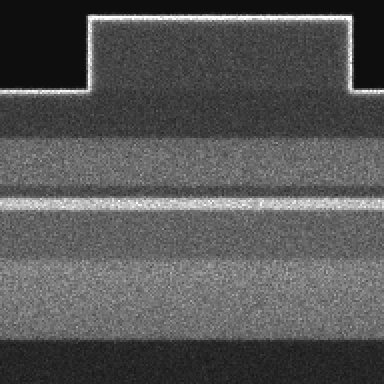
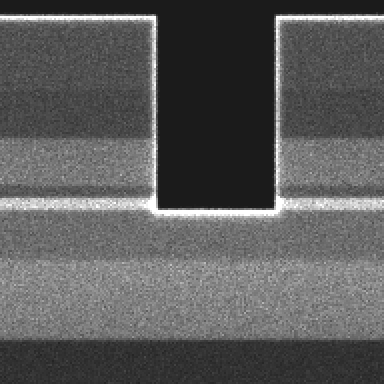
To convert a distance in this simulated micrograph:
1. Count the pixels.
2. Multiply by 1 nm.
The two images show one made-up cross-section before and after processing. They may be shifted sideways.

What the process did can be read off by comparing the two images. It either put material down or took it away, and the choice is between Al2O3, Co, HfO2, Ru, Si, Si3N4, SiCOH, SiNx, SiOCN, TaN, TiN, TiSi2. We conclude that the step removed Co and HfO2 and SiNx and TiN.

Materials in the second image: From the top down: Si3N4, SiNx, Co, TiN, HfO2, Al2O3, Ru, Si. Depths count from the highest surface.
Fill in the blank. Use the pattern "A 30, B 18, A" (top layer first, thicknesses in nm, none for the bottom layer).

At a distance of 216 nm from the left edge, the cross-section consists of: empty 194, Al2O3 50, Ru 80, Si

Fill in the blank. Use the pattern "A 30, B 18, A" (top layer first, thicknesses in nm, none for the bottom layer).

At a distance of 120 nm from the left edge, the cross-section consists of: Si3N4 74, SiNx 48, Co 48, TiN 12, HfO2 12, Al2O3 50, Ru 80, Si